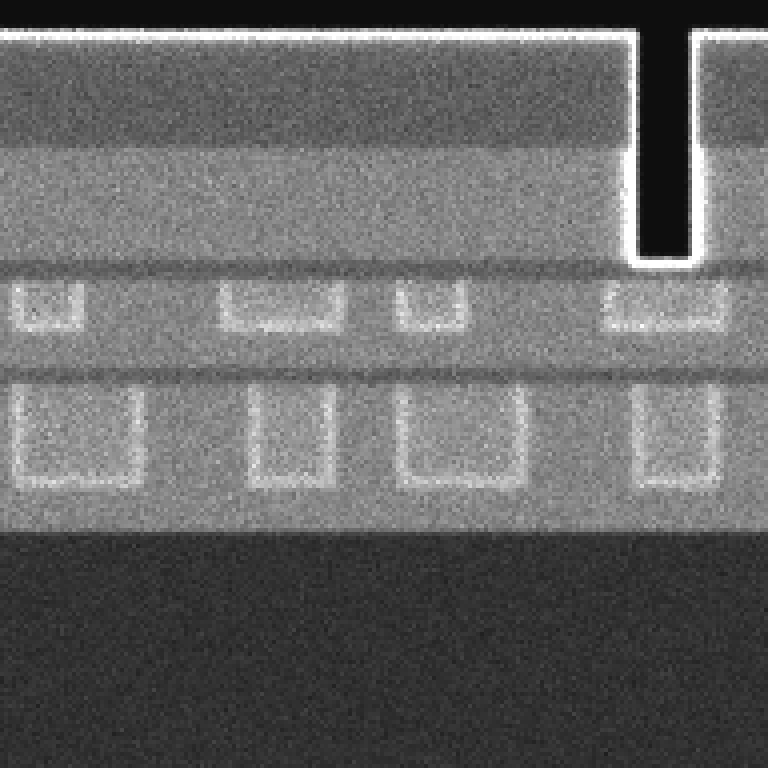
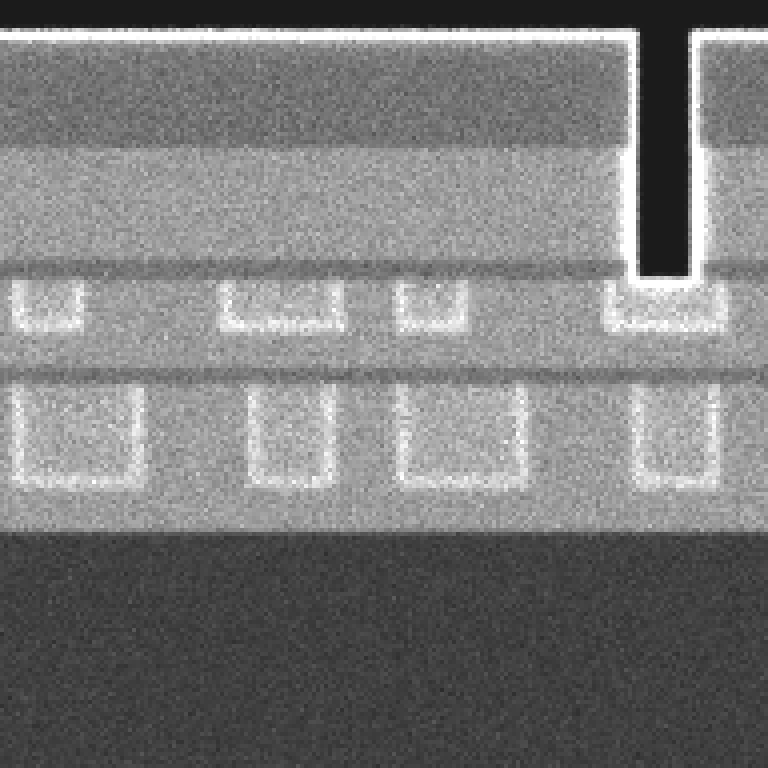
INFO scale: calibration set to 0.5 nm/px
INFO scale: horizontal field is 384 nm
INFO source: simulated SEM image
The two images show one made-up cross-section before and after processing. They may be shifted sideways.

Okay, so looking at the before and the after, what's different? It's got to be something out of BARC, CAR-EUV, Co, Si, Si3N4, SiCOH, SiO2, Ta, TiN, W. Si3N4, removed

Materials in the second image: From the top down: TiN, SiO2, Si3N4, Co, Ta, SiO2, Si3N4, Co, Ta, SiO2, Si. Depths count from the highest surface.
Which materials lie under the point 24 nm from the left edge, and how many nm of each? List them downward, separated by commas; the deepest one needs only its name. TiN 58, SiO2 56, Si3N4 10, Co 20, Ta 6, SiO2 18, Si3N4 8, Co 46, Ta 6, SiO2 22, Si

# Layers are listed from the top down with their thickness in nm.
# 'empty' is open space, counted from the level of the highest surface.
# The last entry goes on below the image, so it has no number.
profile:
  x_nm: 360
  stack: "TiN 58, SiO2 56, Si3N4 10, Ta 26, SiO2 18, Si3N4 8, SiO2 74, Si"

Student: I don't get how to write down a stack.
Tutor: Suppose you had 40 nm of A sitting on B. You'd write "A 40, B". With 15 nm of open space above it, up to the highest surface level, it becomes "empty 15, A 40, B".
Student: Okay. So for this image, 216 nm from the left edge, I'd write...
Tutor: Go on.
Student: TiN 58, SiO2 56, Si3N4 10, Co 20, Ta 6, SiO2 18, Si3N4 8, Co 46, Ta 6, SiO2 22, Si